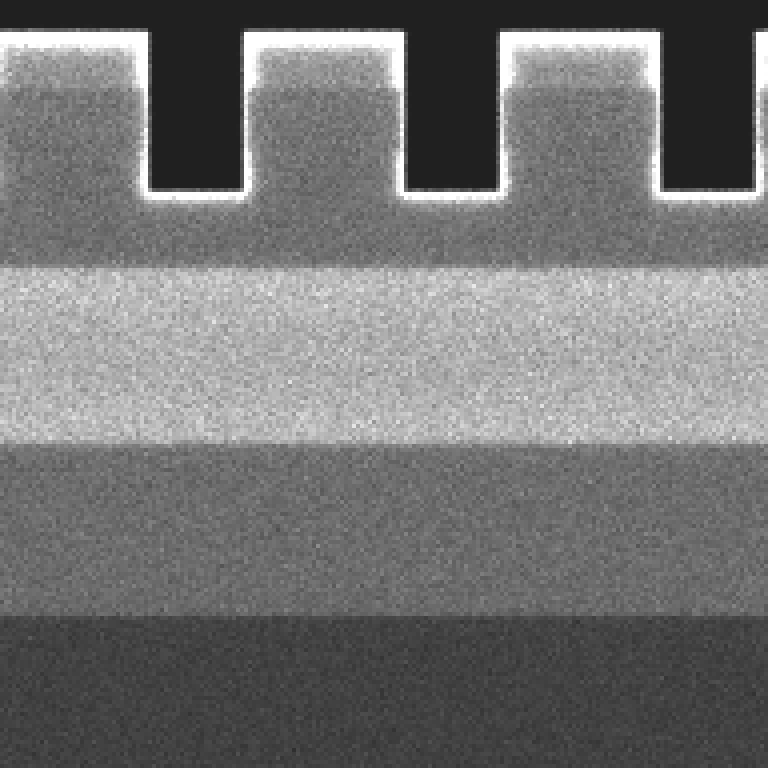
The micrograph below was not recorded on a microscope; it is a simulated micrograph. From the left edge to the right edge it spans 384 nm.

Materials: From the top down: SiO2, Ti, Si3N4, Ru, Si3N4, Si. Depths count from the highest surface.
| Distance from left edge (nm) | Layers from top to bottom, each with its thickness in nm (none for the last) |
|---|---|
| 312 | SiO2 28, Ti 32, Si3N4 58, Ru 88, Si3N4 86, Si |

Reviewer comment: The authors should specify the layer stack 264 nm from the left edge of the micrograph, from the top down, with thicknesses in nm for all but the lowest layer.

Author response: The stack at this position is SiO2 28, Ti 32, Si3N4 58, Ru 88, Si3N4 86, Si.